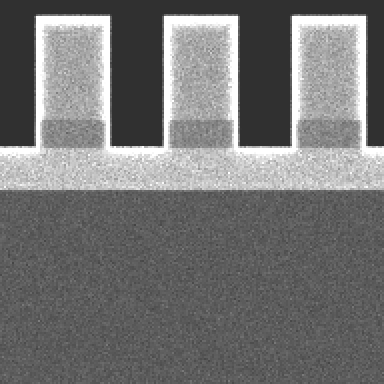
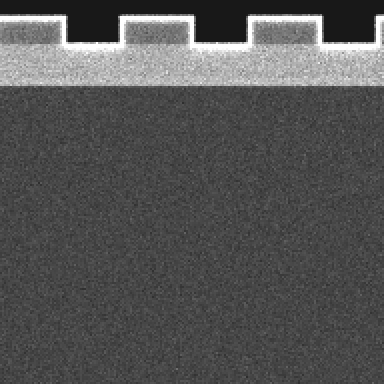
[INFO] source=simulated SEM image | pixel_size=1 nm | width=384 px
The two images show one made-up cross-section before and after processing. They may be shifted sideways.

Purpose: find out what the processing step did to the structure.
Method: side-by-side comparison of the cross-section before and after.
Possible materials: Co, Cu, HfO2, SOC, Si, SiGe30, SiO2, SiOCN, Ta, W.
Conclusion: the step removed SOC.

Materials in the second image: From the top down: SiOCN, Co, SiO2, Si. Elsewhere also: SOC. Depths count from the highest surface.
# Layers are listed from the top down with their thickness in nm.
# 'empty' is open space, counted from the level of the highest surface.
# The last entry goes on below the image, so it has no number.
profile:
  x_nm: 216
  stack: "empty 28, Co 34, SiO2 8, Si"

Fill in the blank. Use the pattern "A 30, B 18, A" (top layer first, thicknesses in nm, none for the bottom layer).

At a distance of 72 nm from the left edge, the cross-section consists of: empty 28, Co 34, SiO2 8, Si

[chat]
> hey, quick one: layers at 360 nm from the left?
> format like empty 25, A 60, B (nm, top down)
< empty 28, Co 34, SiO2 8, Si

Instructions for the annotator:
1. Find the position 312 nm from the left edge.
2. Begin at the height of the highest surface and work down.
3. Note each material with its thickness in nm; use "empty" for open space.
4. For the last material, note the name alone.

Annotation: SiOCN 28, Co 34, SiO2 8, Si